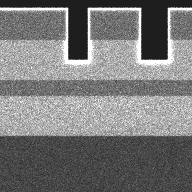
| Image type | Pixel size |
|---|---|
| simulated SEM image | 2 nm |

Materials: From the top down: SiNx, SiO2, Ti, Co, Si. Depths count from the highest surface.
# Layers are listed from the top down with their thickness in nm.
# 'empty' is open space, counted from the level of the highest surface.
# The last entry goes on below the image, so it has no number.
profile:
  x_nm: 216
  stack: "SiNx 64, SiO2 80, Ti 32, Co 80, Si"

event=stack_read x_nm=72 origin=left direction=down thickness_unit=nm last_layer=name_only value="SiNx 64, SiO2 80, Ti 32, Co 80, Si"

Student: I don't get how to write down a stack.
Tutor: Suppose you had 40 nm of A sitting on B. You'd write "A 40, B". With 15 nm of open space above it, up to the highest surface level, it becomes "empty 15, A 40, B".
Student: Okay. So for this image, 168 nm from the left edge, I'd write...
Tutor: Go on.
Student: empty 104, SiO2 40, Ti 32, Co 80, Si